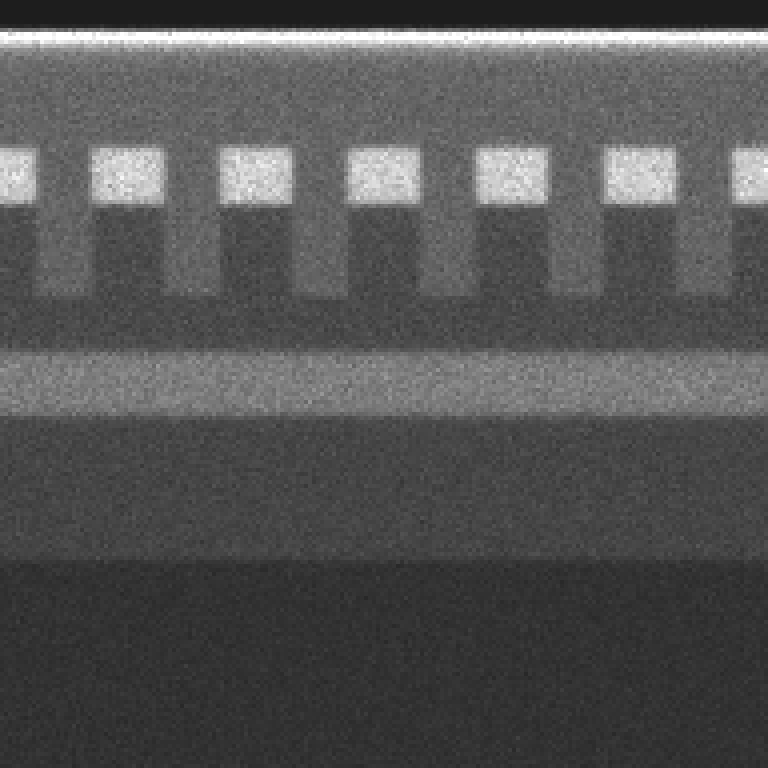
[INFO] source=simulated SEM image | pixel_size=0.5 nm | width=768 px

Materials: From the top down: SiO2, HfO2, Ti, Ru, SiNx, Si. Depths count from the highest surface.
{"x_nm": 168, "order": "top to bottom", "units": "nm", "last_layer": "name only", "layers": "SiO2 132, Ti 28, Ru 32, SiNx 72, Si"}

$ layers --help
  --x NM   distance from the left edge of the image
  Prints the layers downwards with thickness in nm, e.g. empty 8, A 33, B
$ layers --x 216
SiO2 132, Ti 28, Ru 32, SiNx 72, Si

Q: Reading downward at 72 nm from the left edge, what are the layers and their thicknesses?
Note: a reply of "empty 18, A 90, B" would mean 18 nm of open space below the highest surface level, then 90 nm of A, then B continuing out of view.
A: SiO2 58, HfO2 28, Ti 74, Ru 32, SiNx 72, Si